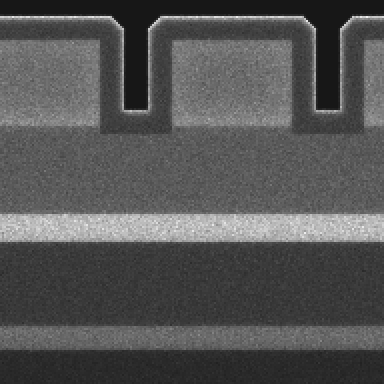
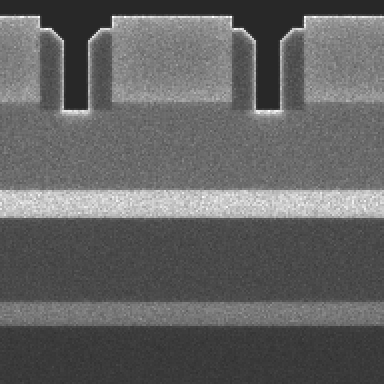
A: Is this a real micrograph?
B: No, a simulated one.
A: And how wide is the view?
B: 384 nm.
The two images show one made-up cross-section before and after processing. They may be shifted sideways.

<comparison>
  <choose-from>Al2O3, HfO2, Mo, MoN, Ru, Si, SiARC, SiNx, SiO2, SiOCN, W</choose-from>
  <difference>SiNx removed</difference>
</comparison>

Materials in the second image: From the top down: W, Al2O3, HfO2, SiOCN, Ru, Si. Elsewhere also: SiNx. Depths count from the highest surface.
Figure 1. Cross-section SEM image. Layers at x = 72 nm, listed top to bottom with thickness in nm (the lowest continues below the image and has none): empty 94, Al2O3 80, HfO2 28, SiOCN 84, Ru 24, Si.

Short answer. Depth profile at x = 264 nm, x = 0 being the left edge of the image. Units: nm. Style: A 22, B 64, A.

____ empty 94, Al2O3 80, HfO2 28, SiOCN 84, Ru 24, Si